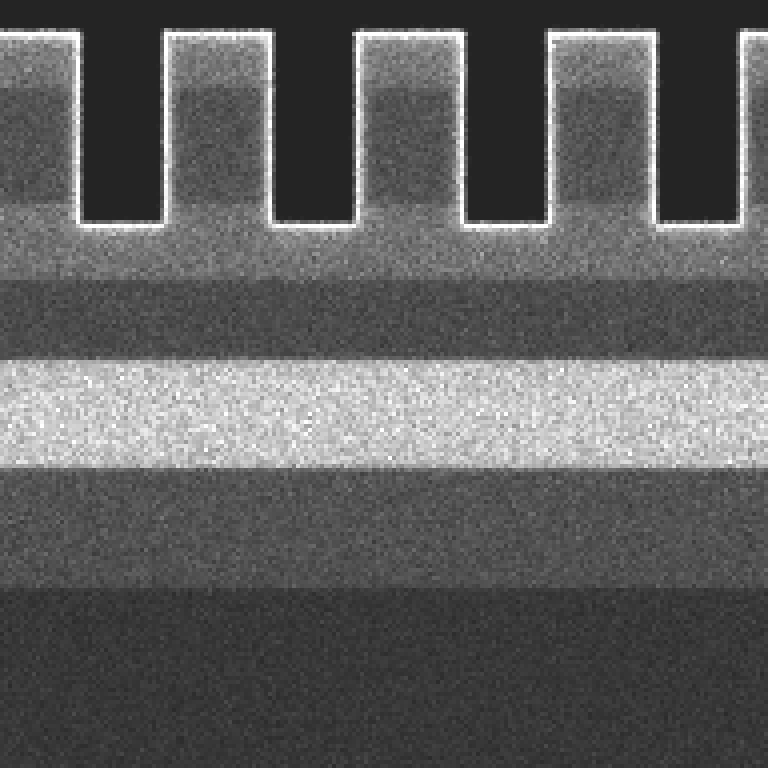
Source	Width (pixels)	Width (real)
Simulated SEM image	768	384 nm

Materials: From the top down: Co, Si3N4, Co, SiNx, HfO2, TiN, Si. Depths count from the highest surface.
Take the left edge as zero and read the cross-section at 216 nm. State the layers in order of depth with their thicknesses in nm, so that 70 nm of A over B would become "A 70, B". Co 28, Si3N4 58, Co 38, SiNx 40, HfO2 54, TiN 60, Si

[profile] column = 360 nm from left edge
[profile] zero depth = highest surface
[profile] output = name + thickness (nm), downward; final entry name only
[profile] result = empty 96, Co 28, SiNx 40, HfO2 54, TiN 60, Si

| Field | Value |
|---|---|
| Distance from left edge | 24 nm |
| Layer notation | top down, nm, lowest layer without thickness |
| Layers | Co 28, Si3N4 58, Co 38, SiNx 40, HfO2 54, TiN 60, Si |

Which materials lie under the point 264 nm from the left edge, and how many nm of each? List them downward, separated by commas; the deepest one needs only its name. empty 96, Co 28, SiNx 40, HfO2 54, TiN 60, Si